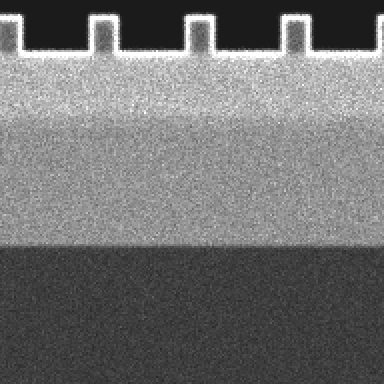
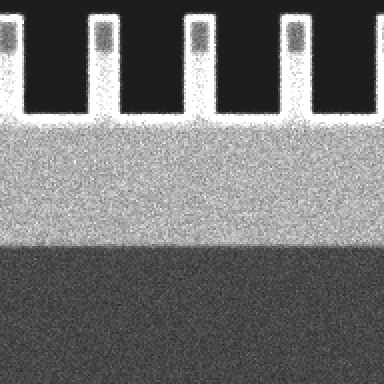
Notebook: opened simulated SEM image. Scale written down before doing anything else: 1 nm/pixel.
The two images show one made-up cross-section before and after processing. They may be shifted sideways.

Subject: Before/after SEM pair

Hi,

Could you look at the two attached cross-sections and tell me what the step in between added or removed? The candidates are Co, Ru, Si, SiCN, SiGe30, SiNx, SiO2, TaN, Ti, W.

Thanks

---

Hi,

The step removed Ru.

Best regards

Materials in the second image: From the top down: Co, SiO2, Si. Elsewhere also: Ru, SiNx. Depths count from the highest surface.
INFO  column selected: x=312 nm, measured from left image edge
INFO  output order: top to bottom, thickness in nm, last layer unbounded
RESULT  empty 100, Co 12, SiO2 118, Si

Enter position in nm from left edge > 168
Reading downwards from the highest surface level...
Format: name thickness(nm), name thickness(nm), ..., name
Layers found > empty 100, Co 12, SiO2 118, Si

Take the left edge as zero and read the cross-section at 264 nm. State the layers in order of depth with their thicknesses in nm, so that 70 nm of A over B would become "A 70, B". empty 100, Co 12, SiO2 118, Si